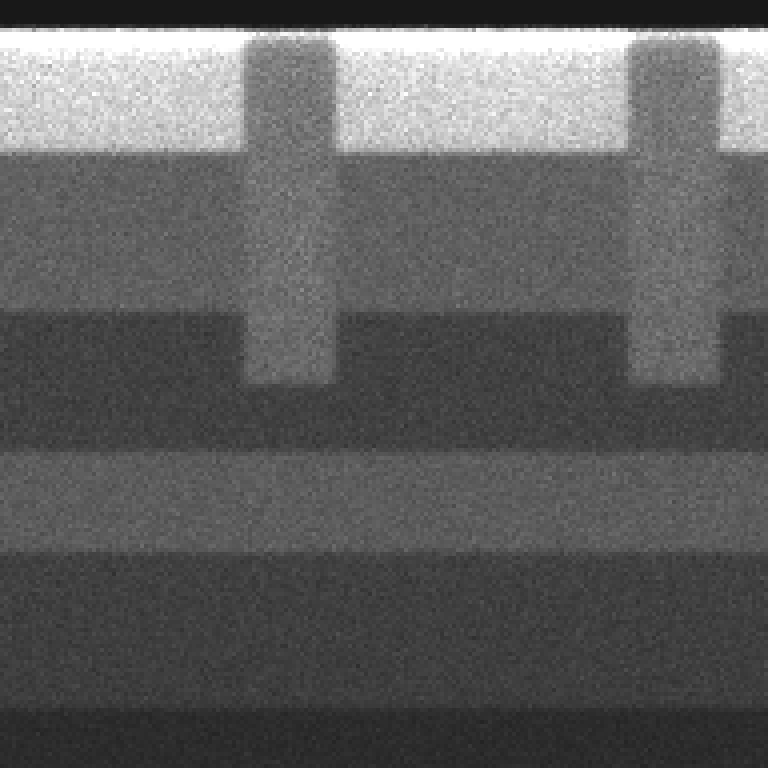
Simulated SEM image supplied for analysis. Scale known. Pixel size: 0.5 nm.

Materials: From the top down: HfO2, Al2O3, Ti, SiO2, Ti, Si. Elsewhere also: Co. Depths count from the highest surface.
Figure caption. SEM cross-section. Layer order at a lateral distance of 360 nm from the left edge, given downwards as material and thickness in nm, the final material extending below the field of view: HfO2 60, Al2O3 80, Ti 70, SiO2 50, Ti 78, Si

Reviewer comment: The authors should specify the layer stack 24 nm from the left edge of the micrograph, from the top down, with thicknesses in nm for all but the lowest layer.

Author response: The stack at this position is HfO2 60, Al2O3 80, Ti 70, SiO2 50, Ti 78, Si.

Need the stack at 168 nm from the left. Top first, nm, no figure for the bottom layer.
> HfO2 60, Al2O3 80, Ti 70, SiO2 50, Ti 78, Si